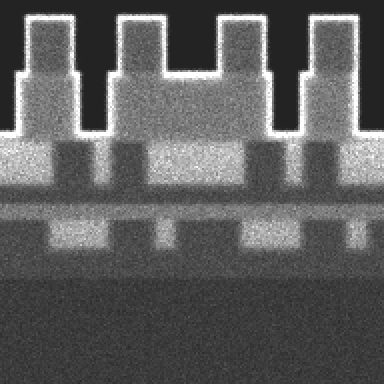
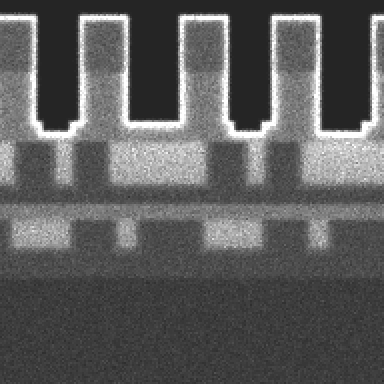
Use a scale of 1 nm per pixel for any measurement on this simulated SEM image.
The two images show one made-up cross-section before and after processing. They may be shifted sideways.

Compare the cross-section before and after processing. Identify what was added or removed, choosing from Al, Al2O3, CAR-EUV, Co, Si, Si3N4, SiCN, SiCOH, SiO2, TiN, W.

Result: SiO2 removed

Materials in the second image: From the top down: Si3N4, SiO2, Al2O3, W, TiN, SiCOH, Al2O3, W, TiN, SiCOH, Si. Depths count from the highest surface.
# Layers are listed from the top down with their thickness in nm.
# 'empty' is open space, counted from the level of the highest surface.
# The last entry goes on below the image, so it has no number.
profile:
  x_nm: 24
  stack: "Si3N4 56, SiO2 60, Al2O3 10, SiCOH 62, Al2O3 16, W 28, TiN 6, SiCOH 24, Si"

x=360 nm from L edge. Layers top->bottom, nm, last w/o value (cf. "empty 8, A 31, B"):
empty 116, Al2O3 10, W 42, TiN 6, SiCOH 14, Al2O3 16, SiCOH 58, Si